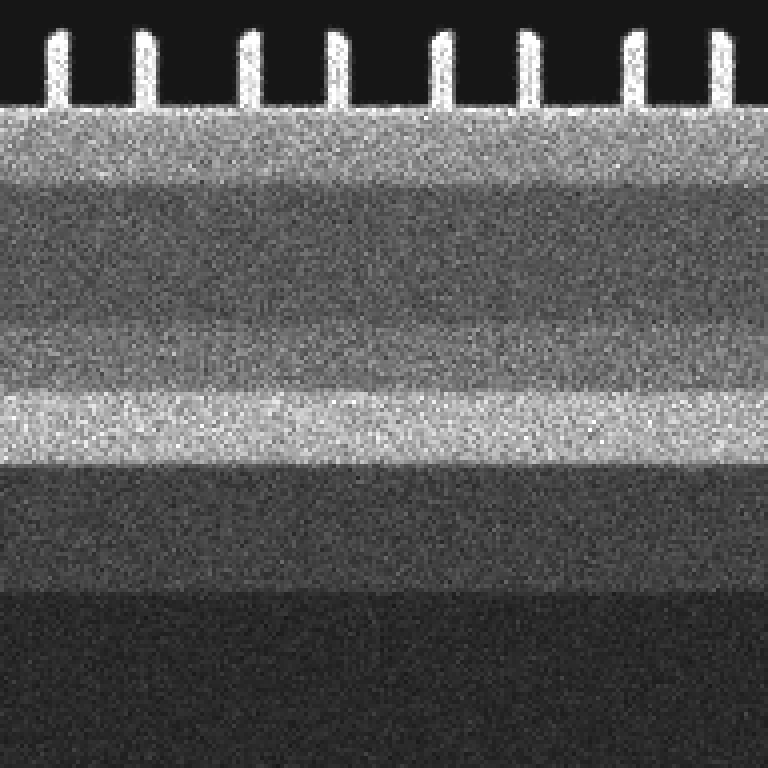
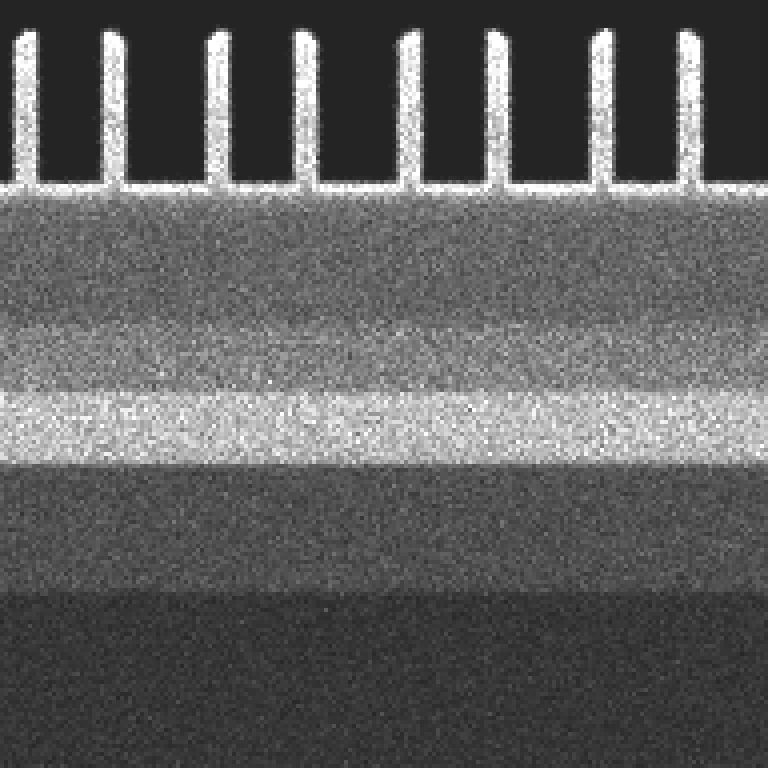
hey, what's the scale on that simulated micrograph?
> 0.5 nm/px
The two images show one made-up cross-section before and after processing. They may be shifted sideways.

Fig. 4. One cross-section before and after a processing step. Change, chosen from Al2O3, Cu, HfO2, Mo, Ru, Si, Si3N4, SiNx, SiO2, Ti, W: W removed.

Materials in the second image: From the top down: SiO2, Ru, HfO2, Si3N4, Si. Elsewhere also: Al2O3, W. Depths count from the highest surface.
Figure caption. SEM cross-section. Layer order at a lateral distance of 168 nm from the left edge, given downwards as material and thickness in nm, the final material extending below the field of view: empty 76, SiO2 70, Ru 34, HfO2 36, Si3N4 64, Si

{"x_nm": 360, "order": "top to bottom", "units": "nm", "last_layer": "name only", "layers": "empty 76, SiO2 70, Ru 34, HfO2 36, Si3N4 64, Si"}